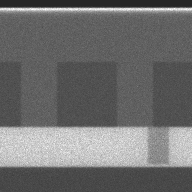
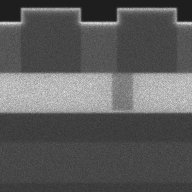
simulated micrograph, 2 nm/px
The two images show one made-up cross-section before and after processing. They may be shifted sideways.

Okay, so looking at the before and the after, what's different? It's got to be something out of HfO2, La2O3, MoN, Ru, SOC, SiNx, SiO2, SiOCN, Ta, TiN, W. SiO2, removed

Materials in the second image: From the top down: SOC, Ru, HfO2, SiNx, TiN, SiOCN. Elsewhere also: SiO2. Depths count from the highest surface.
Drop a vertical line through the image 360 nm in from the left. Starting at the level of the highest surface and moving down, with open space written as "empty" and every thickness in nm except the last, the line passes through empty 28, SiO2 102, HfO2 80, SiNx 58, TiN 82, SiOCN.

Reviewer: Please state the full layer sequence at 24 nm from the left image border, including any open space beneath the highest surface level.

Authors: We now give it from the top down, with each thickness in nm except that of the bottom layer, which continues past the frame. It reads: empty 28, SiO2 102, HfO2 80, SiNx 58, TiN 82, SiOCN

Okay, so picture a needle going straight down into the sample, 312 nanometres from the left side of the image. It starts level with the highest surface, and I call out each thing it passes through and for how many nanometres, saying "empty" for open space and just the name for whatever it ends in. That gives SOC 130, HfO2 80, SiNx 58, TiN 82, SiOCN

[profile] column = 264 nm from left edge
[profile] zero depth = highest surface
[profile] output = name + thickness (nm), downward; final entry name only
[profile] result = SOC 130, Ru 74, HfO2 6, SiNx 58, TiN 82, SiOCN